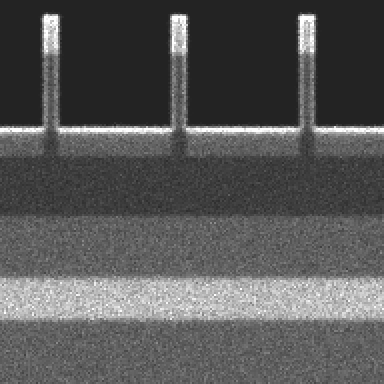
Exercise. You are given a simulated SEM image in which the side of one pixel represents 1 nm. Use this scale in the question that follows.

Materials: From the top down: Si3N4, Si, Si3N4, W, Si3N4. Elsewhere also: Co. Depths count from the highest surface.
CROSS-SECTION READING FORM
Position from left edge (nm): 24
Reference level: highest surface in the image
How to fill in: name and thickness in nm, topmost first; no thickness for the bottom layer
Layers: empty 112, Si3N4 28, Si 60, Si3N4 62, W 42, Si3N4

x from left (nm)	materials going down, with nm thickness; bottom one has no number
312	Co 38, Si 162, Si3N4 62, W 42, Si3N4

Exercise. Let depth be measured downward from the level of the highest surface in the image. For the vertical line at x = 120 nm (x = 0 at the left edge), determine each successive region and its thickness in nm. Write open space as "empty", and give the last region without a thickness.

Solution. empty 112, Si3N4 28, Si 60, Si3N4 62, W 42, Si3N4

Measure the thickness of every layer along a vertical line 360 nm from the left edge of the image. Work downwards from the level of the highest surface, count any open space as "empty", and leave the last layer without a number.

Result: empty 112, Si3N4 28, Si 60, Si3N4 62, W 42, Si3N4